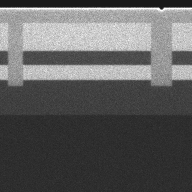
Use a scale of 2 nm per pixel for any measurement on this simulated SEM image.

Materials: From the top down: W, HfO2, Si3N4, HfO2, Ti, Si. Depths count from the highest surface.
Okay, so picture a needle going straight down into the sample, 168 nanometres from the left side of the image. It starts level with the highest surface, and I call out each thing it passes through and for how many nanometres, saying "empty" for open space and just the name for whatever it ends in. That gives W 30, HfO2 56, Si3N4 28, HfO2 30, Ti 70, Si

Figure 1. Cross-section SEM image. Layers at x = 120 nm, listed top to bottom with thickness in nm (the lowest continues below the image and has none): W 30, HfO2 56, Si3N4 28, HfO2 30, Ti 70, Si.